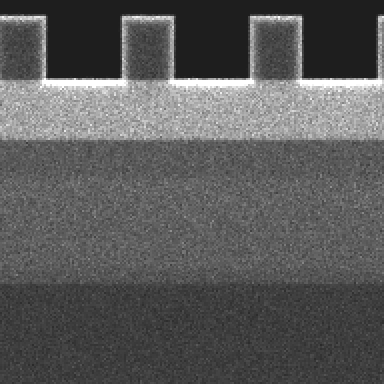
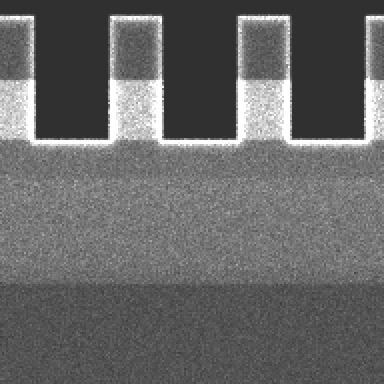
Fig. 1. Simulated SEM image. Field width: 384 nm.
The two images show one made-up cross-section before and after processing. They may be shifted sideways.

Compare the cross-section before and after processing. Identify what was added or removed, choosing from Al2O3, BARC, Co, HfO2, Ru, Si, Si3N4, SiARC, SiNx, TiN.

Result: HfO2 removed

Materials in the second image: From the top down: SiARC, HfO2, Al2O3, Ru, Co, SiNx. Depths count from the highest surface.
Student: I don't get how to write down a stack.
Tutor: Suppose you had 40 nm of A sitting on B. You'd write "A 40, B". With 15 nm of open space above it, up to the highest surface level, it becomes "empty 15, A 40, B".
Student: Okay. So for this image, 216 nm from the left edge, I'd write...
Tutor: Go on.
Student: empty 124, Al2O3 38, Ru 92, Co 14, SiNx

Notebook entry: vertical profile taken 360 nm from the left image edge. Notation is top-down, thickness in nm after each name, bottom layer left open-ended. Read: empty 124, Al2O3 38, Ru 92, Co 14, SiNx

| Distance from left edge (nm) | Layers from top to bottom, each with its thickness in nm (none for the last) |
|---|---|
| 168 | empty 124, Al2O3 38, Ru 92, Co 14, SiNx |